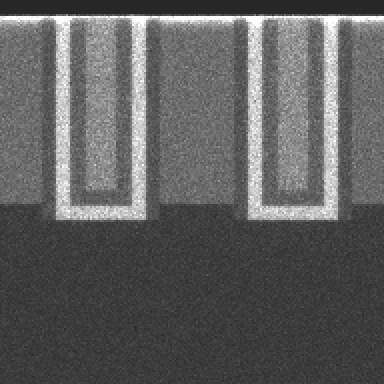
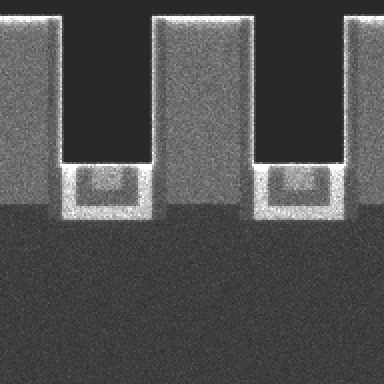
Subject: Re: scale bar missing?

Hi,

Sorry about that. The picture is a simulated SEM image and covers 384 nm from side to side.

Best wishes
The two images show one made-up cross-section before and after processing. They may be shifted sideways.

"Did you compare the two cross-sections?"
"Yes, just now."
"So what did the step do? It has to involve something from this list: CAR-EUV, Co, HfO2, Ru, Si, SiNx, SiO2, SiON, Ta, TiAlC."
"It removed Co and HfO2 and TiAlC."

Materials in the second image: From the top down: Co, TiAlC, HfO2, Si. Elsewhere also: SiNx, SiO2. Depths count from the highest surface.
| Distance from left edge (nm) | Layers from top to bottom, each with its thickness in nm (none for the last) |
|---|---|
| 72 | empty 148, HfO2 56, Si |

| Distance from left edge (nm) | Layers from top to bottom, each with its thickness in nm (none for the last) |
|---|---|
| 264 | empty 148, HfO2 56, Si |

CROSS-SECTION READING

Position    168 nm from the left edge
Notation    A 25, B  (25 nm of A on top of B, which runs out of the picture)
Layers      SiO2 188, Si